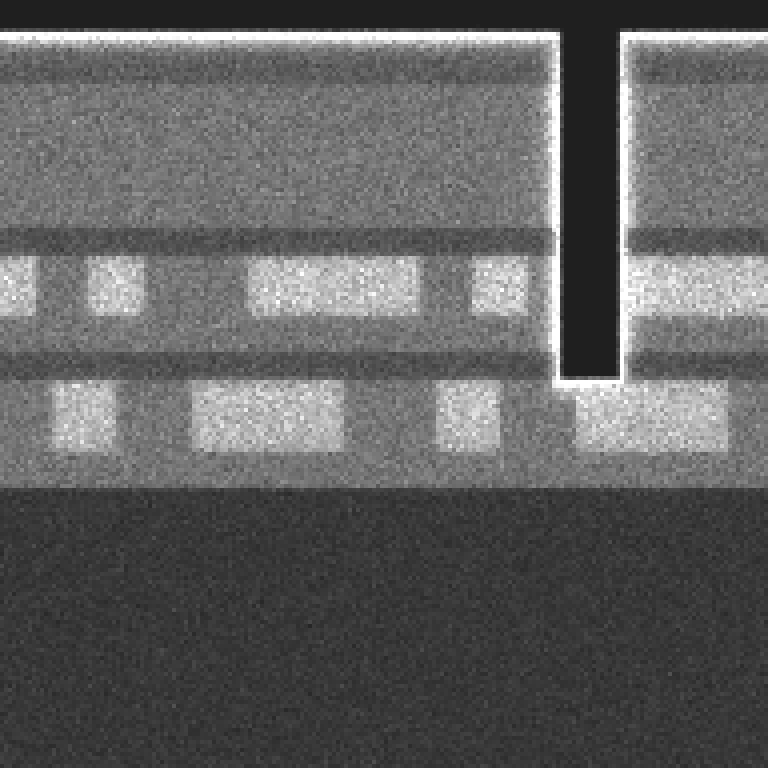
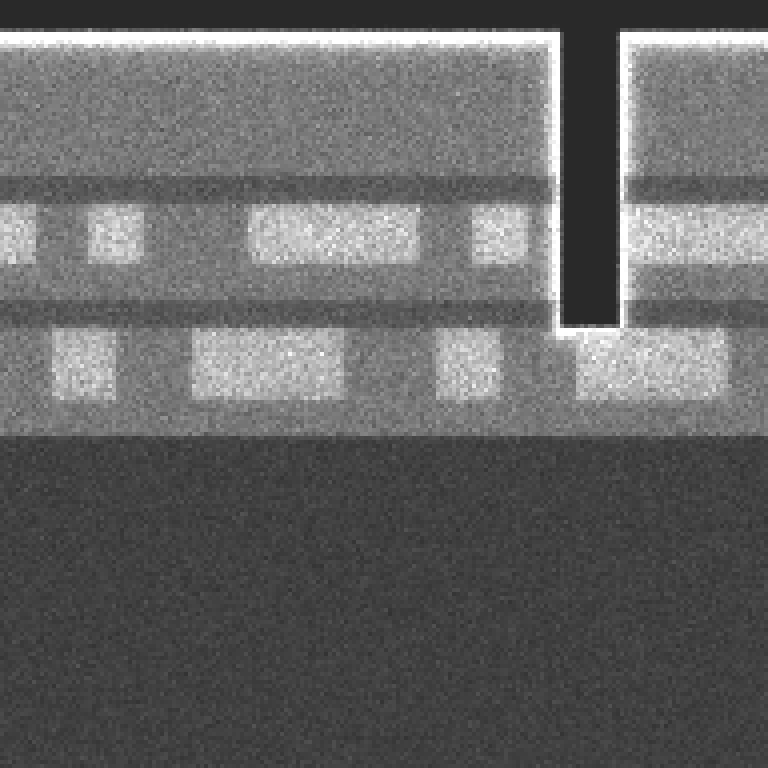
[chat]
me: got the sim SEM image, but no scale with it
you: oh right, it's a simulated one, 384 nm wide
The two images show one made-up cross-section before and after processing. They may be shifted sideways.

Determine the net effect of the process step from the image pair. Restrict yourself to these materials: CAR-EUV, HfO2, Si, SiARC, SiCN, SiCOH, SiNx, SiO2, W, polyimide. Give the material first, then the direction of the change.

SiARC: removed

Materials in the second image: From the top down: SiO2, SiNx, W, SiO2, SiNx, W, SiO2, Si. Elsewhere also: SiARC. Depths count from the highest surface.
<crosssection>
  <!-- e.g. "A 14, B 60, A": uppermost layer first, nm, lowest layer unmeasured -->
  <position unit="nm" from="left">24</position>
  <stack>SiO2 72, SiNx 14, SiO2 48, SiNx 14, SiO2 54, Si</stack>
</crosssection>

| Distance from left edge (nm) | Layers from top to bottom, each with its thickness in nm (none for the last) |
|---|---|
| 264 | SiO2 72, SiNx 14, SiO2 48, SiNx 14, SiO2 54, Si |